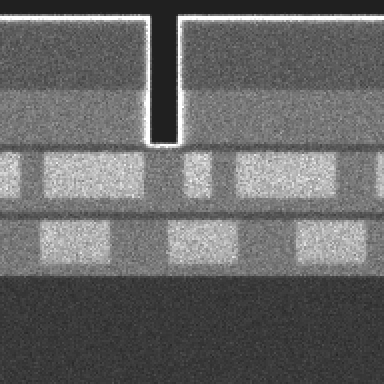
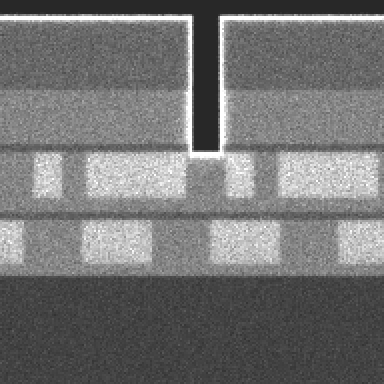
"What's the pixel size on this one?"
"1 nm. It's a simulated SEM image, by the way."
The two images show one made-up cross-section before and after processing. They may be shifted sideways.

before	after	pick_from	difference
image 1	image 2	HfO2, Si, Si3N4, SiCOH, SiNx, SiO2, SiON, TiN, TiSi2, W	SiNx removed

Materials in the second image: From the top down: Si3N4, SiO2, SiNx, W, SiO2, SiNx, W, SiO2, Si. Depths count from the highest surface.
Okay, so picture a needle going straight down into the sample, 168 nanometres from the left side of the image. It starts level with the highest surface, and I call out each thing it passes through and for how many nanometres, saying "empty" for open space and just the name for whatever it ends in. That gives Si3N4 74, SiO2 54, SiNx 8, W 46, SiO2 14, SiNx 8, SiO2 56, Si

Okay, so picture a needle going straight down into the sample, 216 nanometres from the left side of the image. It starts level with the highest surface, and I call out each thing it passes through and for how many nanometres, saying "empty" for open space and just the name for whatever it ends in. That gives empty 136, SiO2 60, SiNx 8, W 44, SiO2 12, Si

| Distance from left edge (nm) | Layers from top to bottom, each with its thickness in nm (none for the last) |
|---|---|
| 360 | Si3N4 74, SiO2 54, SiNx 8, W 46, SiO2 14, SiNx 8, W 44, SiO2 12, Si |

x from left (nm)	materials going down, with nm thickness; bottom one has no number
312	Si3N4 74, SiO2 54, SiNx 8, W 46, SiO2 14, SiNx 8, SiO2 56, Si